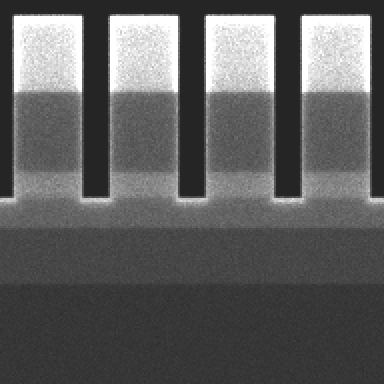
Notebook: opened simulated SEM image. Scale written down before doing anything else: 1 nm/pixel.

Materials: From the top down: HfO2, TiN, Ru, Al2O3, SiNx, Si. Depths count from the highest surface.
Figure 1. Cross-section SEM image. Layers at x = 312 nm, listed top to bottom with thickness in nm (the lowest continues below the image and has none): HfO2 76, TiN 80, Ru 26, Al2O3 30, SiNx 56, Si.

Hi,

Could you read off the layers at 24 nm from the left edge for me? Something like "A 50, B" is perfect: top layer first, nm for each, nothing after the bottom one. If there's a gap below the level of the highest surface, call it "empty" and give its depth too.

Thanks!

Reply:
HfO2 76, TiN 80, Ru 26, Al2O3 30, SiNx 56, Si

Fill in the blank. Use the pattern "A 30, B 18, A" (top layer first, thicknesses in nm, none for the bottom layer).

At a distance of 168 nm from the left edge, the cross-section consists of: HfO2 76, TiN 80, Ru 26, Al2O3 30, SiNx 56, Si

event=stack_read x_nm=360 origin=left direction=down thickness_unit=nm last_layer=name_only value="HfO2 76, TiN 80, Ru 26, Al2O3 30, SiNx 56, Si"